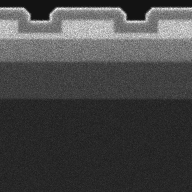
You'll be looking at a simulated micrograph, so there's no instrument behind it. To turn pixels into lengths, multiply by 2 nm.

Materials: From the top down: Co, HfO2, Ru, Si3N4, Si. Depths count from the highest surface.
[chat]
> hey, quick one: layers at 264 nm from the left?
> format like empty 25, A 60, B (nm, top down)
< empty 26, Co 24, HfO2 12, Ru 46, Si3N4 74, Si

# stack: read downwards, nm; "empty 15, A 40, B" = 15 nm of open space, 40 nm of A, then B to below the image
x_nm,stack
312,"Co 50, HfO2 12, Ru 46, Si3N4 74, Si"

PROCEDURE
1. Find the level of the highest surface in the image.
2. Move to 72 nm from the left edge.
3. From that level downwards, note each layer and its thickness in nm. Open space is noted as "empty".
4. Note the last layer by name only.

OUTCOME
empty 26, Co 24, HfO2 12, Ru 46, Si3N4 74, Si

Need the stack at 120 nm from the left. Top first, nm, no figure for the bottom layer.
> Co 50, HfO2 12, Ru 46, Si3N4 74, Si